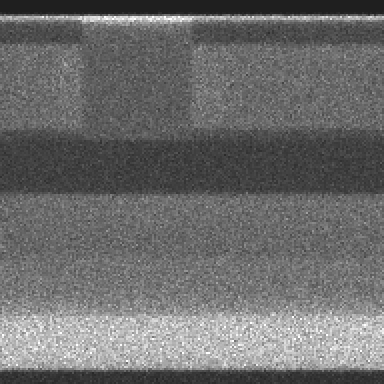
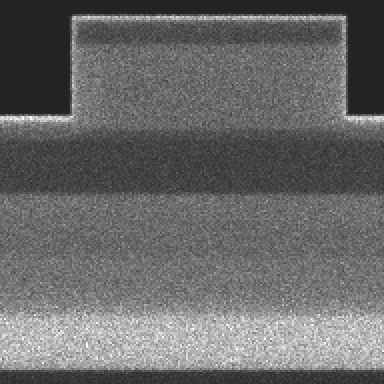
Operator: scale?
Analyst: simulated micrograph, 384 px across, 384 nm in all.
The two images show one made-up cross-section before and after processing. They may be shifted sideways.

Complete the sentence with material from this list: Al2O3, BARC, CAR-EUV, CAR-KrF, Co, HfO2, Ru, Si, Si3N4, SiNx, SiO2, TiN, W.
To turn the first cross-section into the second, Al2O3 must be removed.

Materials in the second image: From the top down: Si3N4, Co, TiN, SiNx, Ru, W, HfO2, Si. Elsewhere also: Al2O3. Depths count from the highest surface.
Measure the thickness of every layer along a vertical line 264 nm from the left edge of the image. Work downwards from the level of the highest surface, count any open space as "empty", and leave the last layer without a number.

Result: Si3N4 28, Co 86, TiN 10, SiNx 54, Ru 64, W 58, HfO2 54, Si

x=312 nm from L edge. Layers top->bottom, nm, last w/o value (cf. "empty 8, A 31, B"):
Si3N4 28, Co 86, TiN 10, SiNx 54, Ru 64, W 58, HfO2 54, Si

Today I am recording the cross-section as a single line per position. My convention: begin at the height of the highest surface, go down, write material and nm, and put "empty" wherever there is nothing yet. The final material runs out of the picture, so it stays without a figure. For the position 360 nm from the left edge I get empty 100, Al2O3 24, SiNx 54, Ru 64, W 58, HfO2 54, Si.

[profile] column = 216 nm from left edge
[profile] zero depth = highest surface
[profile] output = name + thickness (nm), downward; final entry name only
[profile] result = Si3N4 28, Co 86, TiN 10, SiNx 54, Ru 64, W 58, HfO2 54, Si